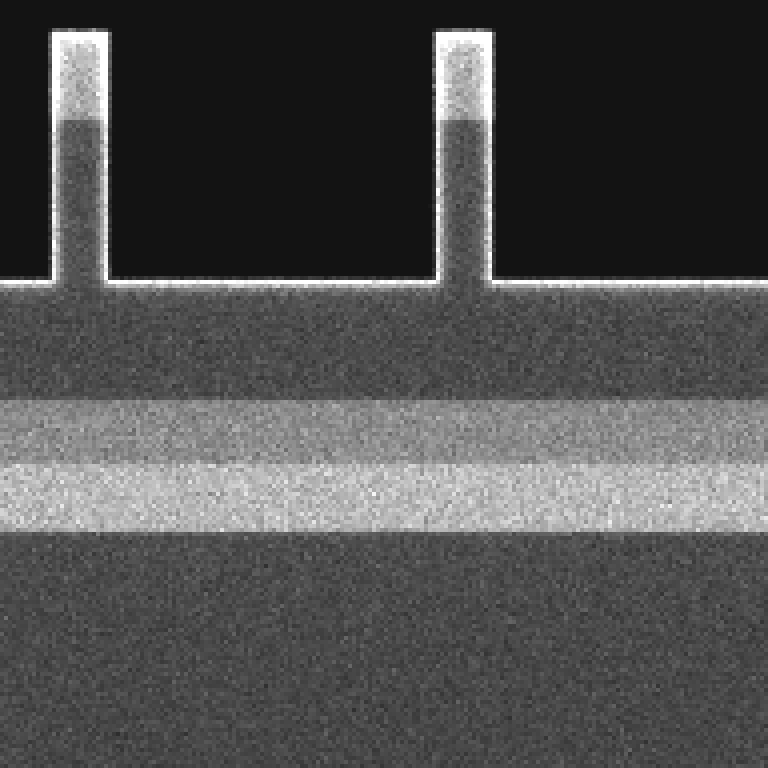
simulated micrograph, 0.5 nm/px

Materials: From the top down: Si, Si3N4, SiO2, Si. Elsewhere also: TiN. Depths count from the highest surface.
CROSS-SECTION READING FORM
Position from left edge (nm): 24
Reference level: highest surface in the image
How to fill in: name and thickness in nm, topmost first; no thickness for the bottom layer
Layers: empty 124, Si 60, Si3N4 32, SiO2 34, Si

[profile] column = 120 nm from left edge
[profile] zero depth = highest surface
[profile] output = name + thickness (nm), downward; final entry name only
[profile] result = empty 124, Si 60, Si3N4 32, SiO2 34, Si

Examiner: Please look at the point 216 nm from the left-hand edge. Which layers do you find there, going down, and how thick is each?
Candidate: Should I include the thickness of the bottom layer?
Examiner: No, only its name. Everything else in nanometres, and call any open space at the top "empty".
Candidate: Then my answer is empty 124, Si 60, Si3N4 32, SiO2 34, Si